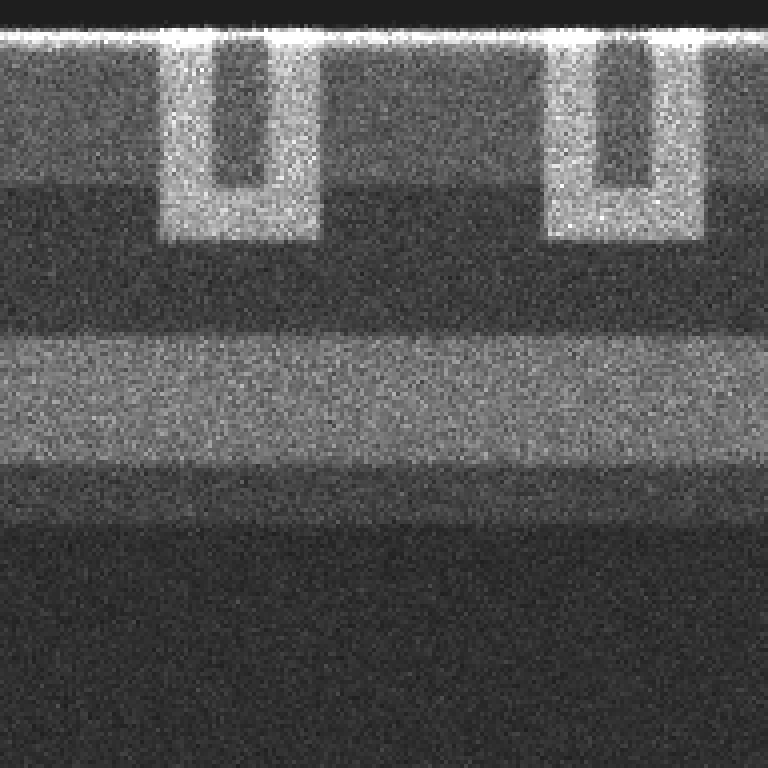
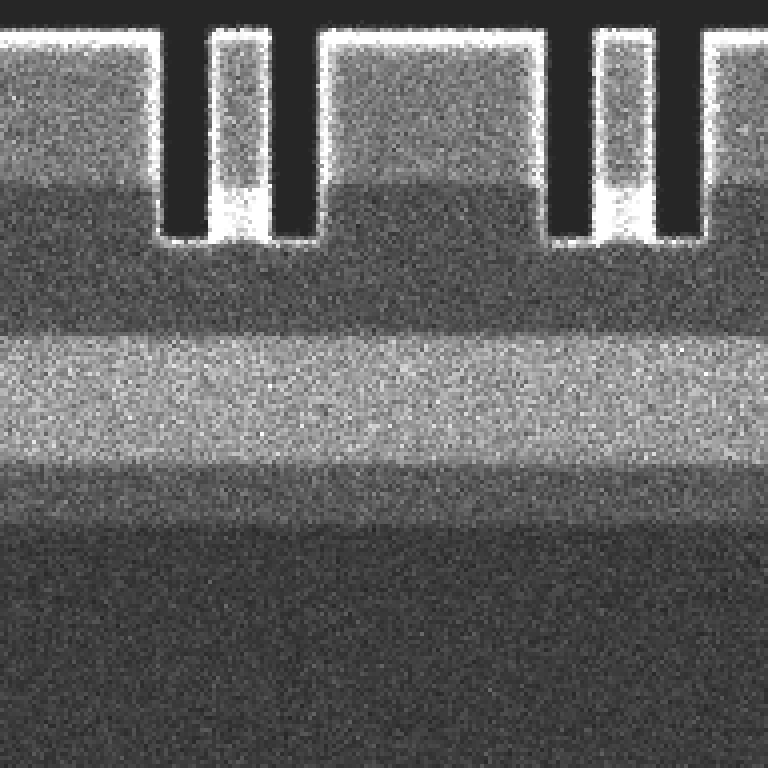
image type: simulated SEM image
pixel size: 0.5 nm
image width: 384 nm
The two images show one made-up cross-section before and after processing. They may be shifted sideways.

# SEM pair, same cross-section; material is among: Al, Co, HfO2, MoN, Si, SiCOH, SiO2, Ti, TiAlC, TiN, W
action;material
removed;HfO2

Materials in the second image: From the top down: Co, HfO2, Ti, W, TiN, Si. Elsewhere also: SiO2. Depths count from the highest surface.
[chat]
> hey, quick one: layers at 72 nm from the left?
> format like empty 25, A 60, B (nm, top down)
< SiO2 76, Ti 76, W 64, TiN 30, Si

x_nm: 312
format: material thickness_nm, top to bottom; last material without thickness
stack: Co 78, HfO2 26, Ti 48, W 64, TiN 30, Si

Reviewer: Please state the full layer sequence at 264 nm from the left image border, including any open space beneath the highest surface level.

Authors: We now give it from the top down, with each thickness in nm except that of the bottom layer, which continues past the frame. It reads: SiO2 76, Ti 76, W 64, TiN 30, Si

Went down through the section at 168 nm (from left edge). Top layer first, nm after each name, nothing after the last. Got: SiO2 76, Ti 76, W 64, TiN 30, Si